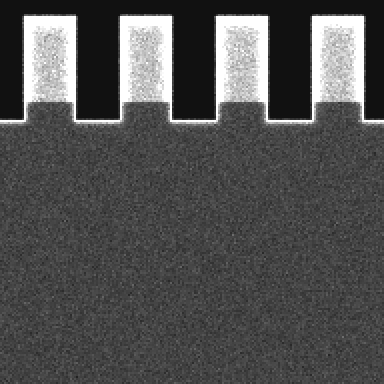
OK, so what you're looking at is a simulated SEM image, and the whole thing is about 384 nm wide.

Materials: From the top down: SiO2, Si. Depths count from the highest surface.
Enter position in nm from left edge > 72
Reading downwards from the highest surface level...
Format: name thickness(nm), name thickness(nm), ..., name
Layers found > SiO2 86, Si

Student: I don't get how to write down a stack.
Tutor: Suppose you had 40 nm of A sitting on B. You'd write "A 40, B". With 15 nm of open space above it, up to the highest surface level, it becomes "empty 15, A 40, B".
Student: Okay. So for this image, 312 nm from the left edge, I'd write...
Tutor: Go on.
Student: SiO2 86, Si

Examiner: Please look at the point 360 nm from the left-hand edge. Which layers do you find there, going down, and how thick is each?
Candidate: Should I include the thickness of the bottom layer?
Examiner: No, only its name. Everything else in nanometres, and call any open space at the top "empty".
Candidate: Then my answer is SiO2 86, Si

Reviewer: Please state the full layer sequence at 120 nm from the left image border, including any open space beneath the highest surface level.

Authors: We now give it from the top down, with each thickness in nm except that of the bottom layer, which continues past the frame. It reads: SiO2 86, Si